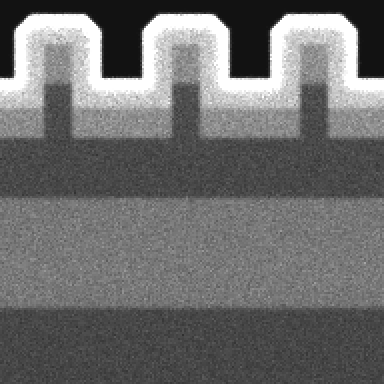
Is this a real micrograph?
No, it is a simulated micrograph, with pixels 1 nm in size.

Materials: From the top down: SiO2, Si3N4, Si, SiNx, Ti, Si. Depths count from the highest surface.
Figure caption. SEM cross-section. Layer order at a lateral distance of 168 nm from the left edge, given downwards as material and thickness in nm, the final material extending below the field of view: SiO2 92, Si3N4 30, Si 60, SiNx 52, Ti 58, Si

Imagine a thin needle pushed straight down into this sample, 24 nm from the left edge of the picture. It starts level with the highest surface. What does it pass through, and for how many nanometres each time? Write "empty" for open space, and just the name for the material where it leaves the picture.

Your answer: empty 6, SiO2 86, Si3N4 30, Si 60, SiNx 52, Ti 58, Si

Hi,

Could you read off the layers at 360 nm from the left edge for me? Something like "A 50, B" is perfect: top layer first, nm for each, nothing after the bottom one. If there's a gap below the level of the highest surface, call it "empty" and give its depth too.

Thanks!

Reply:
empty 64, SiO2 28, Si3N4 30, Si 60, SiNx 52, Ti 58, Si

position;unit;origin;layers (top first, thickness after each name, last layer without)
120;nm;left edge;empty 64, SiO2 28, Si3N4 30, Si 60, SiNx 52, Ti 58, Si